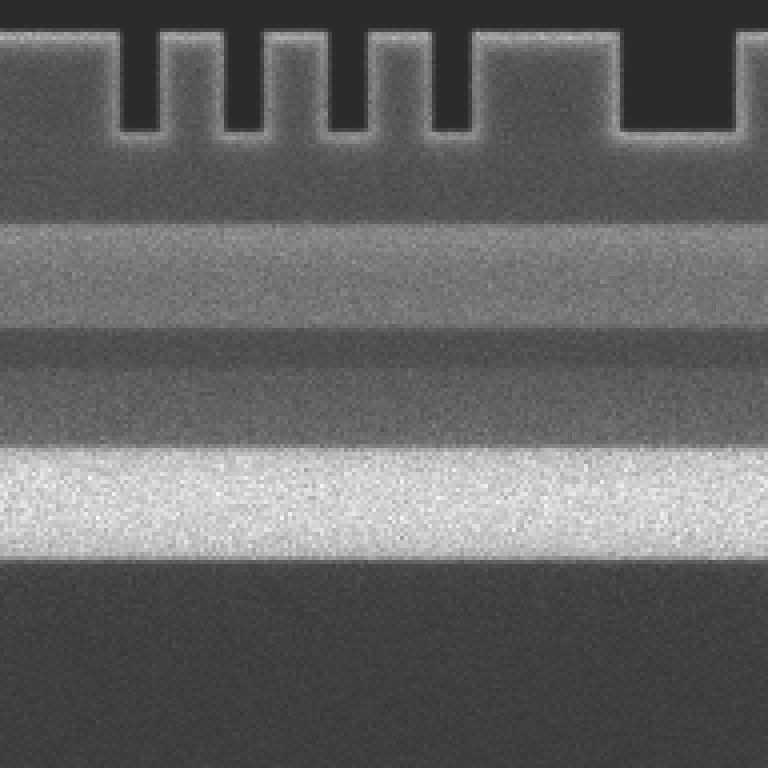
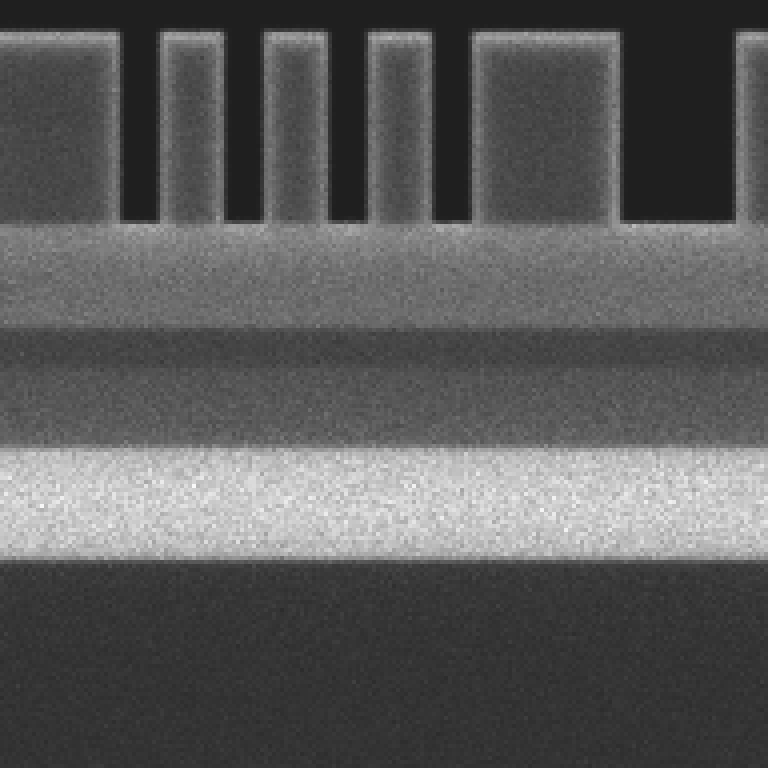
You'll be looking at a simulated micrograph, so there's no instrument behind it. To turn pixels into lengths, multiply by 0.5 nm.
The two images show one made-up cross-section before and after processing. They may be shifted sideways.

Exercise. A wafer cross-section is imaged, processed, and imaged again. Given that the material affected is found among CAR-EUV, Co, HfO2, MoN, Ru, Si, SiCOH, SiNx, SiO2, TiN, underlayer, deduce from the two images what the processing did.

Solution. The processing removed underlayer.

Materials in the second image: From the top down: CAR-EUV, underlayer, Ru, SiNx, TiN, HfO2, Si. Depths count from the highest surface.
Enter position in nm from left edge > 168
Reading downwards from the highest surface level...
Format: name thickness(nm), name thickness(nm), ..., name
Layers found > empty 96, Ru 52, SiNx 20, TiN 40, HfO2 56, Si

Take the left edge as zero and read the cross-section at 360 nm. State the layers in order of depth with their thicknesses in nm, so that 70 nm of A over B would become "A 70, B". empty 96, Ru 52, SiNx 20, TiN 40, HfO2 56, Si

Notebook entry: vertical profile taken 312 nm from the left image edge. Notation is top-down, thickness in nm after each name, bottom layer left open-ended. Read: empty 96, Ru 52, SiNx 20, TiN 40, HfO2 56, Si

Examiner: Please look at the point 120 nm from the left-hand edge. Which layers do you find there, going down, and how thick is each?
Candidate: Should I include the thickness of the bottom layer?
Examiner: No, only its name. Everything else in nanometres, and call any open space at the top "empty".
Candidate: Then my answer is empty 96, Ru 52, SiNx 20, TiN 40, HfO2 56, Si